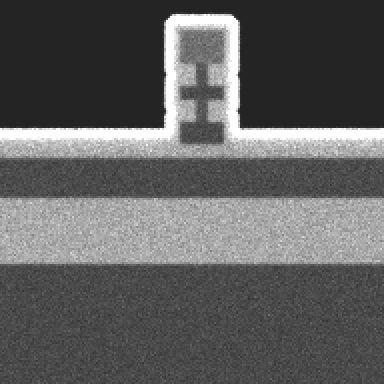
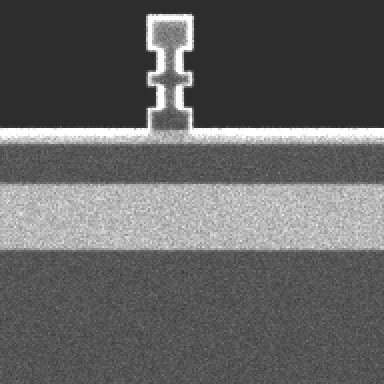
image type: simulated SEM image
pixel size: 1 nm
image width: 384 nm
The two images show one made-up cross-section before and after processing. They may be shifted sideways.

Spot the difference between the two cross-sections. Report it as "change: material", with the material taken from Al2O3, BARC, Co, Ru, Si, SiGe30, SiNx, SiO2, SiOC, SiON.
removed: Al2O3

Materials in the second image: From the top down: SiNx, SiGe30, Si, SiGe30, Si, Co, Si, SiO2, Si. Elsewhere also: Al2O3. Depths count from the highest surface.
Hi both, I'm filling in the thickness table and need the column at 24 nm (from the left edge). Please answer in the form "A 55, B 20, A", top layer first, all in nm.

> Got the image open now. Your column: empty 114, Co 14, Si 40, SiO2 66, Si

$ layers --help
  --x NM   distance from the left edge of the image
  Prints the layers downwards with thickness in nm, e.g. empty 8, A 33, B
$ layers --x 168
SiNx 34, SiGe30 22, Si 14, SiGe30 22, Si 22, Co 14, Si 40, SiO2 66, Si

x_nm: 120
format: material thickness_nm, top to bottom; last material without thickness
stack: empty 114, Co 14, Si 40, SiO2 66, Si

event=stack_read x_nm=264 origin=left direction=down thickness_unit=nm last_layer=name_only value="empty 114, Co 14, Si 40, SiO2 66, Si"